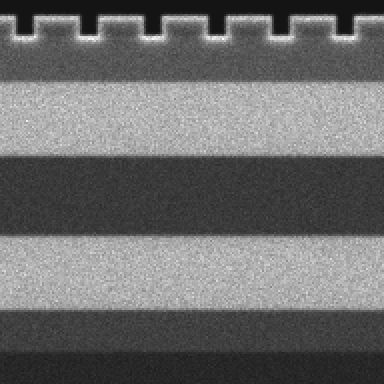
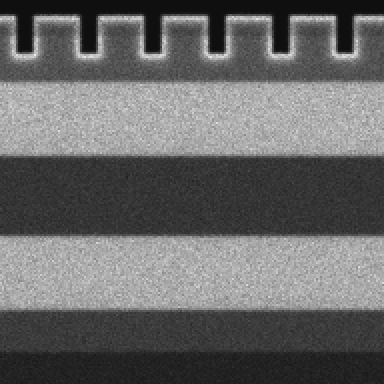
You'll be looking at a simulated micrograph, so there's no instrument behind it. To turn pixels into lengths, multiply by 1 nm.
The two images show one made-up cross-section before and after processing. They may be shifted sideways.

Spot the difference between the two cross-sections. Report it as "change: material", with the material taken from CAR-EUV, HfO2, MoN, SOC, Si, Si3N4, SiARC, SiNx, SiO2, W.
removed: SiO2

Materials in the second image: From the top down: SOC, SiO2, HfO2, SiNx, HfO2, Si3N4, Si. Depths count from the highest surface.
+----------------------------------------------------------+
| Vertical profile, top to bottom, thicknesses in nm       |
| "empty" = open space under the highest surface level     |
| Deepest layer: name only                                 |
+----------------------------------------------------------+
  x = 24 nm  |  empty 38, SiO2 28, HfO2 74, SiNx 80, HfO2 74, Si3N4 42, Si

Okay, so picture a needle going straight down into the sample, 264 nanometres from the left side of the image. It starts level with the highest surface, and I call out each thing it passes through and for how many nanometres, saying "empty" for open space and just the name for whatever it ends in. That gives SOC 20, SiO2 46, HfO2 74, SiNx 80, HfO2 74, Si3N4 42, Si